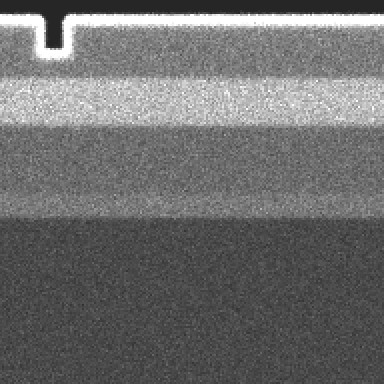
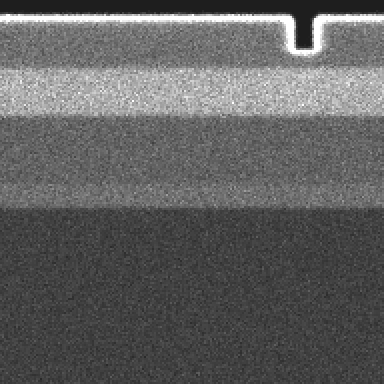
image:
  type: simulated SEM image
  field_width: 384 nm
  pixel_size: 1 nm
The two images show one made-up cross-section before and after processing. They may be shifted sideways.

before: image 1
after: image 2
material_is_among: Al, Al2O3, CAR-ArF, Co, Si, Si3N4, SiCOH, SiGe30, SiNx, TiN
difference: Al2O3, removed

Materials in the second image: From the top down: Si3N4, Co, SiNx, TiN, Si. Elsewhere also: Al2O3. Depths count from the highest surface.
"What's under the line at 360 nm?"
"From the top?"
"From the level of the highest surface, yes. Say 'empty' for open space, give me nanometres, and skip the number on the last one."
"Si3N4 52, Co 48, SiNx 68, TiN 24, Si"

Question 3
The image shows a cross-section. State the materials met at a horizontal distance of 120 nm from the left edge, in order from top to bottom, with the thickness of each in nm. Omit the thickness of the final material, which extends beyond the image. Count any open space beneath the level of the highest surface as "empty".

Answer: Si3N4 52, Co 48, SiNx 68, TiN 24, Si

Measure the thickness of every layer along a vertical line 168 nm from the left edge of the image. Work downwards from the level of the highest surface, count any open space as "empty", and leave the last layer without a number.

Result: Si3N4 52, Co 48, SiNx 68, TiN 24, Si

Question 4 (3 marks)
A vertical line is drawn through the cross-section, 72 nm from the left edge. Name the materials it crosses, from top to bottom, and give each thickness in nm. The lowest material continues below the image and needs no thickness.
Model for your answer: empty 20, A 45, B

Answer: Si3N4 52, Co 48, SiNx 68, TiN 24, Si